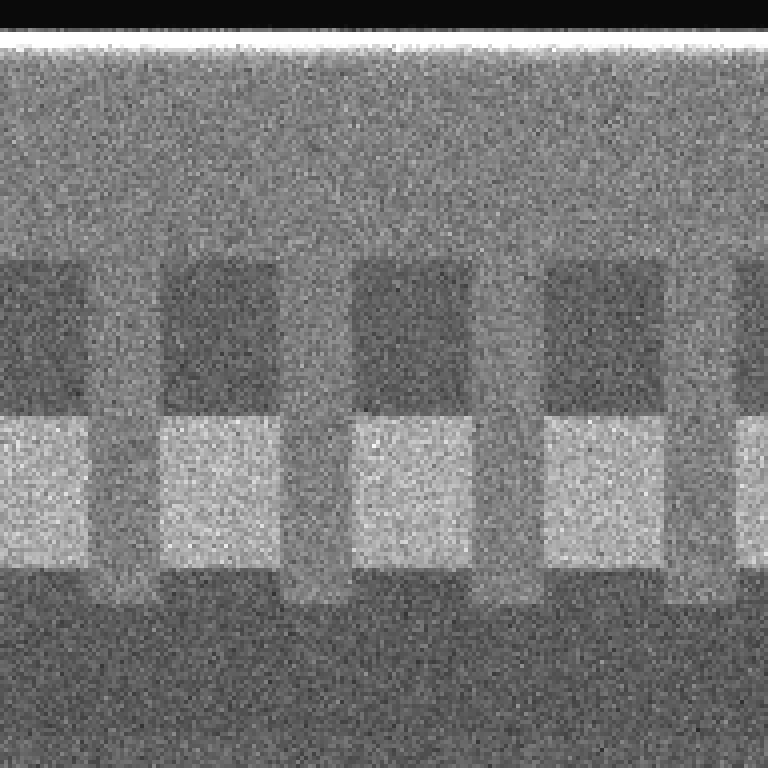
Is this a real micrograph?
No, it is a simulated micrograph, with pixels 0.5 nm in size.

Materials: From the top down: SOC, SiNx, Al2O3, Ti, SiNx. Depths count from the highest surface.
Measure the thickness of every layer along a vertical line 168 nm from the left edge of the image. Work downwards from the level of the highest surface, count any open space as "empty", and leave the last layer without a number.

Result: SOC 286, Ti 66, SiNx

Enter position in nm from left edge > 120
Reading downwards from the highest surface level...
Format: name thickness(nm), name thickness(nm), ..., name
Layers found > SOC 114, SiNx 78, Al2O3 76, Ti 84, SiNx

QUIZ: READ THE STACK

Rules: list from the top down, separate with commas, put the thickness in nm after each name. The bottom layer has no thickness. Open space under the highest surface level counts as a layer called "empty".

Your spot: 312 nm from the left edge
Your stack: SOC 114, SiNx 78, Al2O3 76, Ti 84, SiNx